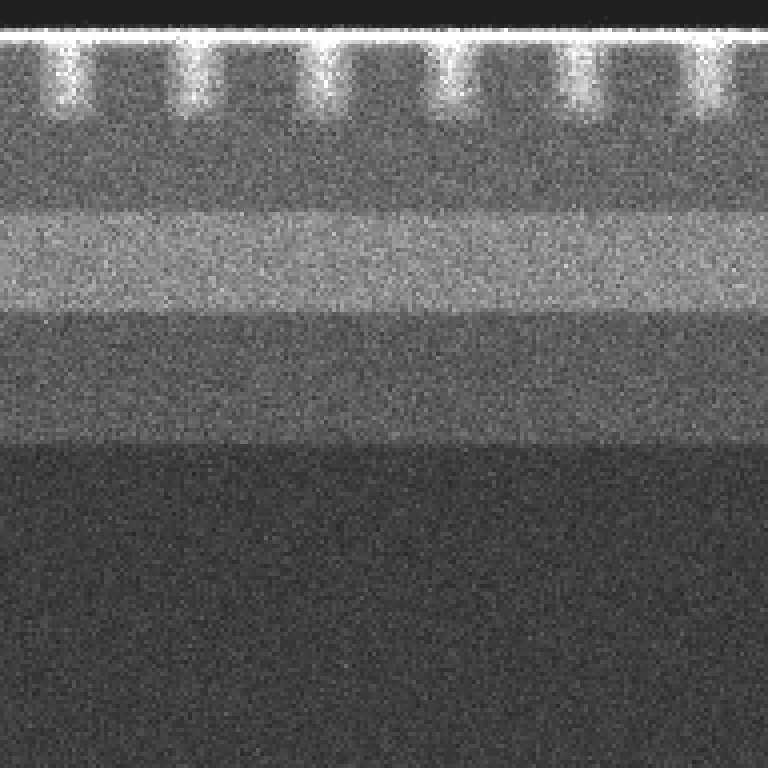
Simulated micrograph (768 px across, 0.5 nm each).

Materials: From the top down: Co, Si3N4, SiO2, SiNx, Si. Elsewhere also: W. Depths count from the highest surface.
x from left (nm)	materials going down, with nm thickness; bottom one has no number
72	Si3N4 90, SiO2 50, SiNx 66, Si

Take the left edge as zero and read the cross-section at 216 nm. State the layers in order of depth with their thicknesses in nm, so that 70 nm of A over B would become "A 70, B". Co 44, Si3N4 46, SiO2 50, SiNx 66, Si